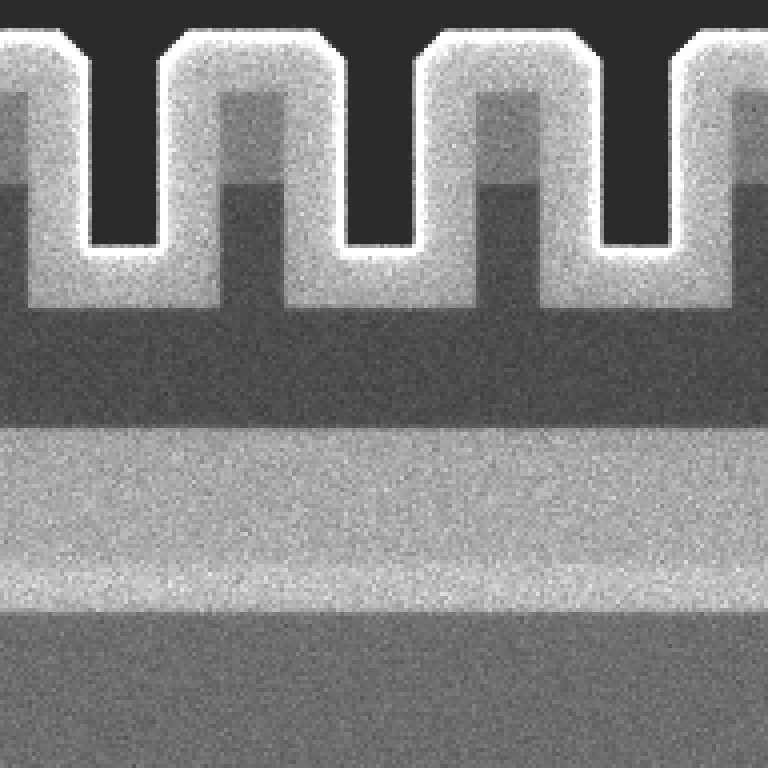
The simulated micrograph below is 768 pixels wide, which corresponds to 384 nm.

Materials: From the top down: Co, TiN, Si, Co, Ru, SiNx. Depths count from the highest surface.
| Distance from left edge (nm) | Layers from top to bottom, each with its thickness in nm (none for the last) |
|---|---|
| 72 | empty 108, Co 30, Si 60, Co 68, Ru 24, SiNx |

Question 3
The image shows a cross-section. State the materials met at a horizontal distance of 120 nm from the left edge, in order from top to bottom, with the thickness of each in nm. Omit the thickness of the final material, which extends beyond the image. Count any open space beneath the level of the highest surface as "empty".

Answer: Co 30, TiN 46, Si 122, Co 68, Ru 24, SiNx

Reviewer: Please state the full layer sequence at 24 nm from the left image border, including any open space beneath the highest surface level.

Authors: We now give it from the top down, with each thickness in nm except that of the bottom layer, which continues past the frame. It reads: Co 138, Si 60, Co 68, Ru 24, SiNx